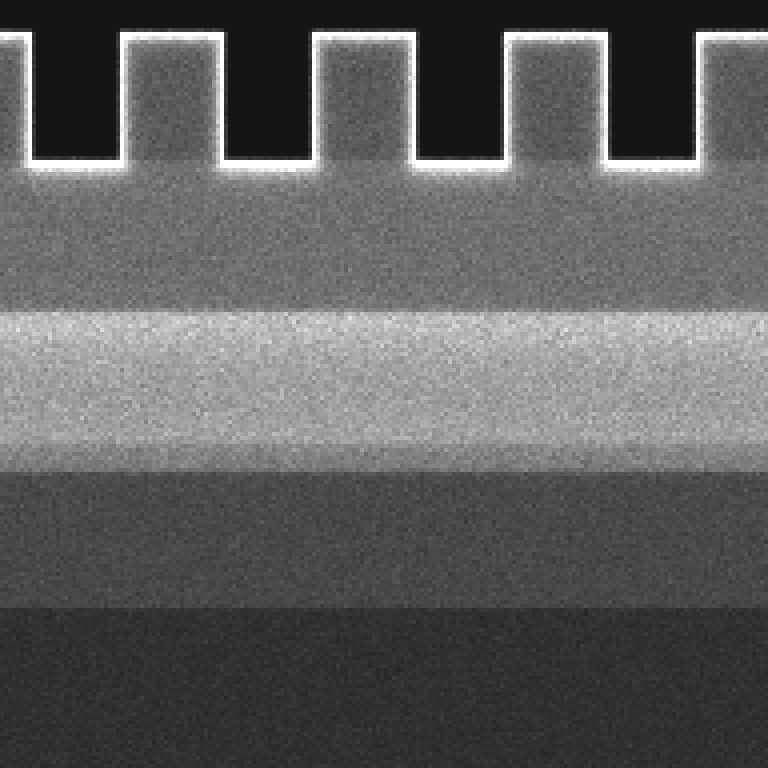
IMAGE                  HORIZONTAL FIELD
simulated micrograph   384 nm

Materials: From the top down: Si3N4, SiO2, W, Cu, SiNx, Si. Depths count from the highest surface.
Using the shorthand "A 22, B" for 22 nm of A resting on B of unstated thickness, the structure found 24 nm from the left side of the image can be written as empty 64, SiO2 76, W 66, Cu 14, SiNx 68, Si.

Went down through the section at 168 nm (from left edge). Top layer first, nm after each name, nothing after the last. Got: Si3N4 64, SiO2 76, W 66, Cu 14, SiNx 68, Si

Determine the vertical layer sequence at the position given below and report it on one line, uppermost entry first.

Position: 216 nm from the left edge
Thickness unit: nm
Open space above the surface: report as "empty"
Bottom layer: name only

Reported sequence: empty 64, SiO2 76, W 66, Cu 14, SiNx 68, Si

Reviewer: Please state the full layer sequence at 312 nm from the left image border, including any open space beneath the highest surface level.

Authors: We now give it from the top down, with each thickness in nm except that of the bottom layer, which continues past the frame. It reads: empty 64, SiO2 76, W 66, Cu 14, SiNx 68, Si